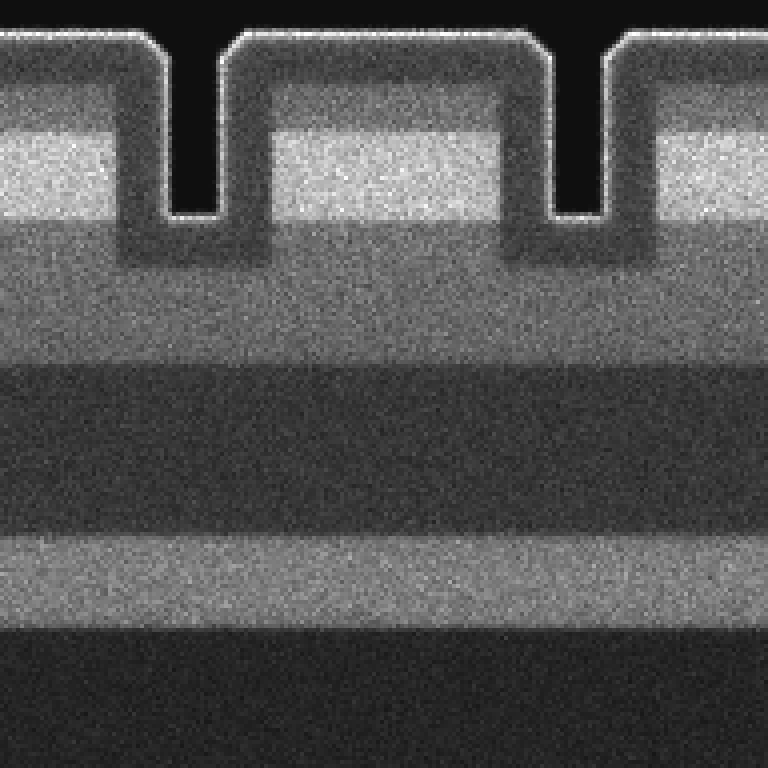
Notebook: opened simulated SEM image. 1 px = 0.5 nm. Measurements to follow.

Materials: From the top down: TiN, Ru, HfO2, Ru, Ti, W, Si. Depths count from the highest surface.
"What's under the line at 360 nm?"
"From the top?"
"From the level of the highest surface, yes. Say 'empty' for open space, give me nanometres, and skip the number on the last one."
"TiN 26, Ru 24, HfO2 44, Ru 72, Ti 86, W 46, Si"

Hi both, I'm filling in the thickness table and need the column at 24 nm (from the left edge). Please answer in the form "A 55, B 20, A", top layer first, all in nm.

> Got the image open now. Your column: TiN 26, Ru 24, HfO2 44, Ru 72, Ti 86, W 46, Si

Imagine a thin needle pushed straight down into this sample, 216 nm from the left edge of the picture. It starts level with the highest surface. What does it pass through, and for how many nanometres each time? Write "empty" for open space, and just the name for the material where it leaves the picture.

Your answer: TiN 26, Ru 24, HfO2 44, Ru 72, Ti 86, W 46, Si